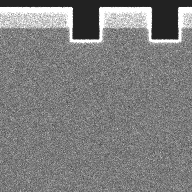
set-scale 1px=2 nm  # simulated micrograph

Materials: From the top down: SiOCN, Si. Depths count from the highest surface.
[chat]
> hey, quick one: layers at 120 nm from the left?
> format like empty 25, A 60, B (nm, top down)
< SiOCN 40, Si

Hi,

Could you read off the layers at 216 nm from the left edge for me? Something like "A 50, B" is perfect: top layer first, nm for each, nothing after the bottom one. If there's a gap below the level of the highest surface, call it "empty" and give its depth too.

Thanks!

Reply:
SiOCN 40, Si